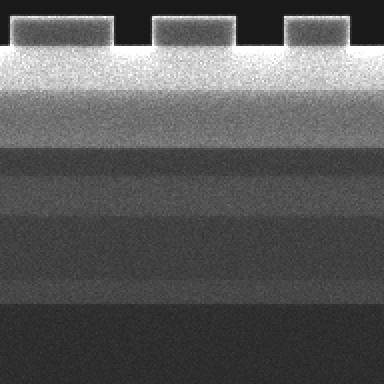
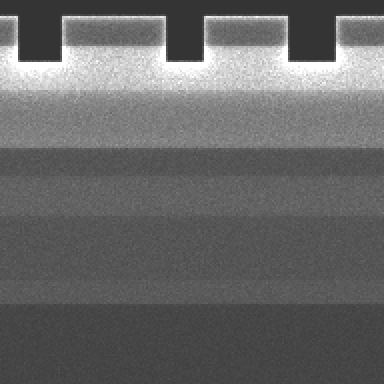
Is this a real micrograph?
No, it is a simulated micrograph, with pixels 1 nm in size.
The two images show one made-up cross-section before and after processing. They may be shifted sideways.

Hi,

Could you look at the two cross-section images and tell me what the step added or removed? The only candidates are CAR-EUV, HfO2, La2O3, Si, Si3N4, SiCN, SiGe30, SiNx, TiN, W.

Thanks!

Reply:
removed HfO2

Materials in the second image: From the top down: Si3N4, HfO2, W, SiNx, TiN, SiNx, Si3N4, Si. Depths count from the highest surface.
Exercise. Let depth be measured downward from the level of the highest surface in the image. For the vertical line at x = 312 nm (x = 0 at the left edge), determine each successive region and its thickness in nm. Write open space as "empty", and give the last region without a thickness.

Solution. empty 46, HfO2 28, W 58, SiNx 28, TiN 40, SiNx 64, Si3N4 24, Si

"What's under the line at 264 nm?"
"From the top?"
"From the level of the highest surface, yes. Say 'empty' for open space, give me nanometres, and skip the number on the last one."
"Si3N4 30, HfO2 44, W 58, SiNx 28, TiN 40, SiNx 64, Si3N4 24, Si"